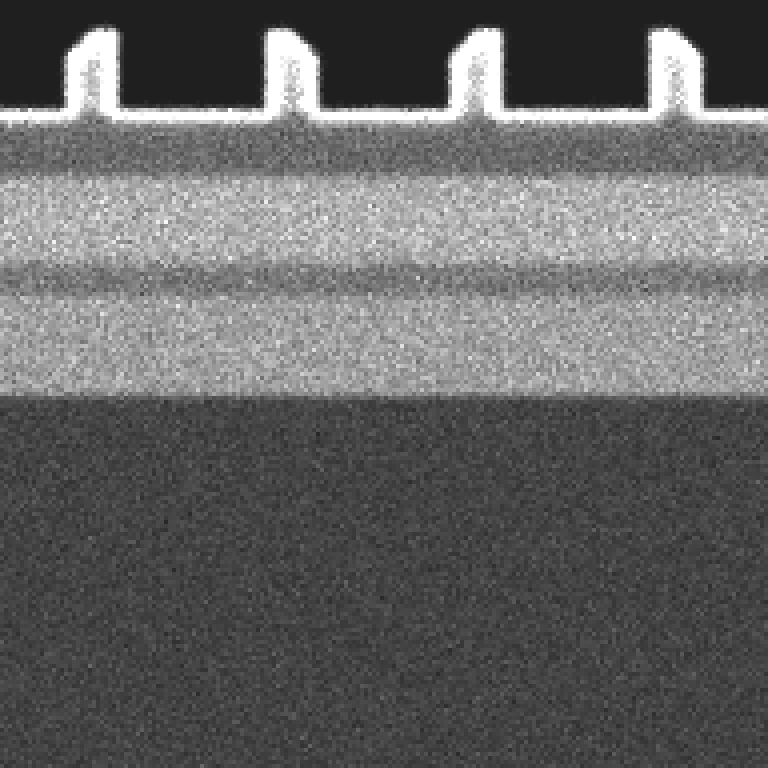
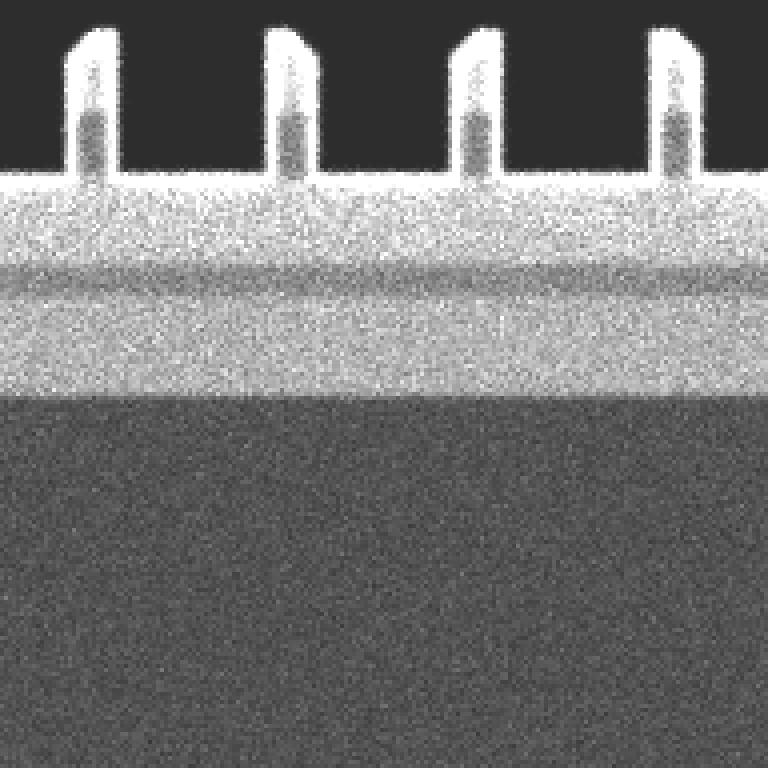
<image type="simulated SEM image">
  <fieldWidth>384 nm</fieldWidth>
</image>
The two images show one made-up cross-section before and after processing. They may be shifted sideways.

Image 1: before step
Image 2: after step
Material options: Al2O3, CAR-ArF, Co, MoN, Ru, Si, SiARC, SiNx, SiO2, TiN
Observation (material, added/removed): SiNx, removed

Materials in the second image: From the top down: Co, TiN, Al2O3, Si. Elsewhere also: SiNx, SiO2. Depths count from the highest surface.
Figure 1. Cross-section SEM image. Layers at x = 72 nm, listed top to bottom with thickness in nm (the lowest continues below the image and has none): empty 72, Co 44, TiN 16, Al2O3 50, Si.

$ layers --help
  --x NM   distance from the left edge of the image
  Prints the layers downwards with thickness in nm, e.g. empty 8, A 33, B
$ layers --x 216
empty 72, Co 44, TiN 16, Al2O3 50, Si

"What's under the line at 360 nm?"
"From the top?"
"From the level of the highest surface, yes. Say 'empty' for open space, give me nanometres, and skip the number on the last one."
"empty 72, Co 44, TiN 16, Al2O3 50, Si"